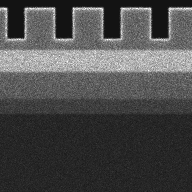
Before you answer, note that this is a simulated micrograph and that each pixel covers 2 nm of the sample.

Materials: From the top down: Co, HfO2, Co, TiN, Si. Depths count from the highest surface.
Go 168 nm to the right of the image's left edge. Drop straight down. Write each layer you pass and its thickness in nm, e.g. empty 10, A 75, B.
Co 84, HfO2 44, Co 54, TiN 30, Si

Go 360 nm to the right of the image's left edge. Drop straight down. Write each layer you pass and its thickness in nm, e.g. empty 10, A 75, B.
Co 84, HfO2 44, Co 54, TiN 30, Si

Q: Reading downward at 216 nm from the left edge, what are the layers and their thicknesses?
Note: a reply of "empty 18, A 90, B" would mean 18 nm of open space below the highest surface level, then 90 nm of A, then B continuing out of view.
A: empty 62, Co 22, HfO2 44, Co 54, TiN 30, Si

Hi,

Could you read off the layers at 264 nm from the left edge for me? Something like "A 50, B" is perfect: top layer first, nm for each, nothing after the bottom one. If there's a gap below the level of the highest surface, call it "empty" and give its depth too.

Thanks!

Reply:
Co 84, HfO2 44, Co 54, TiN 30, Si